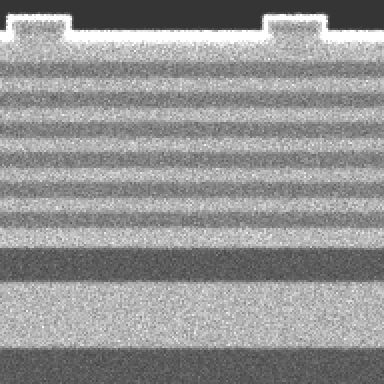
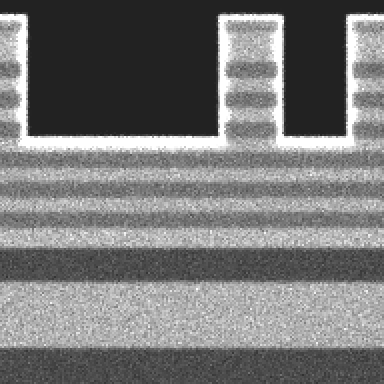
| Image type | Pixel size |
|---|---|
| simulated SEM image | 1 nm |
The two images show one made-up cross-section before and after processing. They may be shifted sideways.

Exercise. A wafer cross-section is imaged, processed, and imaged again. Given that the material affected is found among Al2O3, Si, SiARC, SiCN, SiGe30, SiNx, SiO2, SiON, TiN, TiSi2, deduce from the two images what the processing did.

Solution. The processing removed SiNx and SiO2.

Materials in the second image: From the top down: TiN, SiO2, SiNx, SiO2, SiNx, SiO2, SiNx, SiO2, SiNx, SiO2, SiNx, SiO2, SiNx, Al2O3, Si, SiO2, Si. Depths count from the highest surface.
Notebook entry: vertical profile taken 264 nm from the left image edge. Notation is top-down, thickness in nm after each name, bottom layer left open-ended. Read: TiN 16, SiO2 30, SiNx 16, SiO2 14, SiNx 16, SiO2 14, SiNx 16, SiO2 14, SiNx 16, SiO2 14, SiNx 16, SiO2 14, SiNx 16, Al2O3 20, Si 34, SiO2 66, Si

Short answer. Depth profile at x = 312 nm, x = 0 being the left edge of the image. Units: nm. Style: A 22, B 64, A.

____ empty 122, SiO2 14, SiNx 16, SiO2 14, SiNx 16, SiO2 14, SiNx 16, Al2O3 20, Si 34, SiO2 66, Si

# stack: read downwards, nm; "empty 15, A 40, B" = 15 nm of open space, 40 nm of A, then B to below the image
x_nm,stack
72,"empty 122, SiO2 14, SiNx 16, SiO2 14, SiNx 16, SiO2 14, SiNx 16, Al2O3 20, Si 34, SiO2 66, Si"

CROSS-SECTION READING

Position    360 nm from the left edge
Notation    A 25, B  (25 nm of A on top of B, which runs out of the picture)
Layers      TiN 16, SiO2 30, SiNx 16, SiO2 14, SiNx 16, SiO2 14, SiNx 16, SiO2 14, SiNx 16, SiO2 14, SiNx 16, SiO2 14, SiNx 16, Al2O3 20, Si 34, SiO2 66, Si